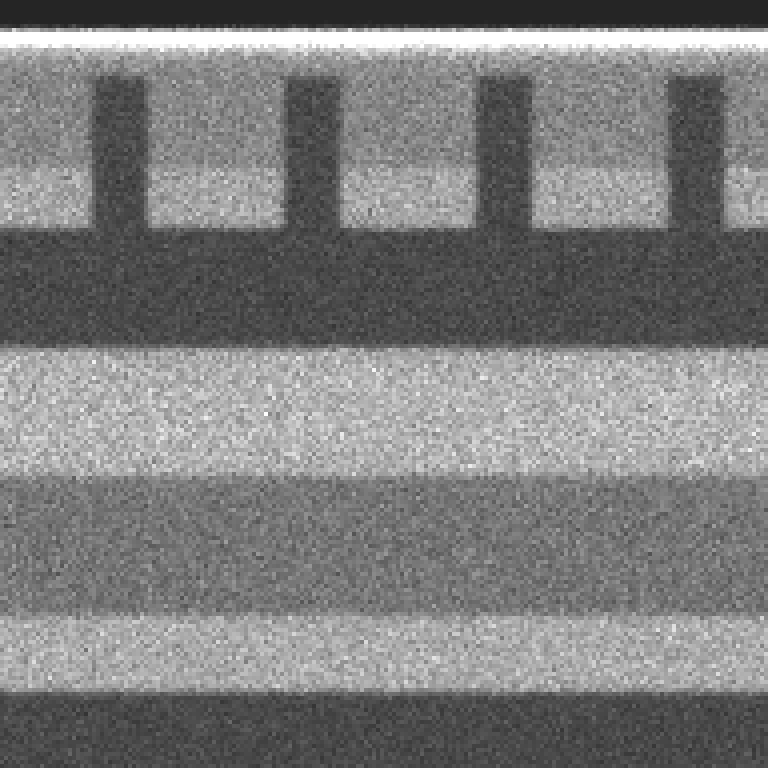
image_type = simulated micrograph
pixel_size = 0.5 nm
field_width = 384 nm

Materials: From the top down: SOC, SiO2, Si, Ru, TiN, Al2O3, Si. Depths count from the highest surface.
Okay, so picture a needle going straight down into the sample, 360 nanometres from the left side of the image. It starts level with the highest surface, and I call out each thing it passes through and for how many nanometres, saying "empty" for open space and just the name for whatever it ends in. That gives SOC 22, Si 136, Ru 64, TiN 70, Al2O3 38, Si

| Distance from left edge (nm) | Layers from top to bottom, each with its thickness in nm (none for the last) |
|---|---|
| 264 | SOC 22, Si 136, Ru 64, TiN 70, Al2O3 38, Si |